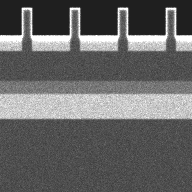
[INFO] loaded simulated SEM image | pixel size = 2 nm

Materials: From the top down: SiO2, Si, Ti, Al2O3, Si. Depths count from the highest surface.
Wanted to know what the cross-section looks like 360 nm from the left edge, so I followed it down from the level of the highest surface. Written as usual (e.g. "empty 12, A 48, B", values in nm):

empty 56, SiO2 30, Si 60, Ti 26, Al2O3 50, Si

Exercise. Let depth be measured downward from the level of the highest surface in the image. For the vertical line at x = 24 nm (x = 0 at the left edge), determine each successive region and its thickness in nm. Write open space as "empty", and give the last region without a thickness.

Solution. empty 56, SiO2 30, Si 60, Ti 26, Al2O3 50, Si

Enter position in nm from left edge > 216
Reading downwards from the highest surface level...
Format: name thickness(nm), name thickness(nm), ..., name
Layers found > empty 56, SiO2 30, Si 60, Ti 26, Al2O3 50, Si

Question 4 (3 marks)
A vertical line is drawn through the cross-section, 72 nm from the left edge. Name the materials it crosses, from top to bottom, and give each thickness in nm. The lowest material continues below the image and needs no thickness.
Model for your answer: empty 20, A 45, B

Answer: empty 56, SiO2 30, Si 60, Ti 26, Al2O3 50, Si